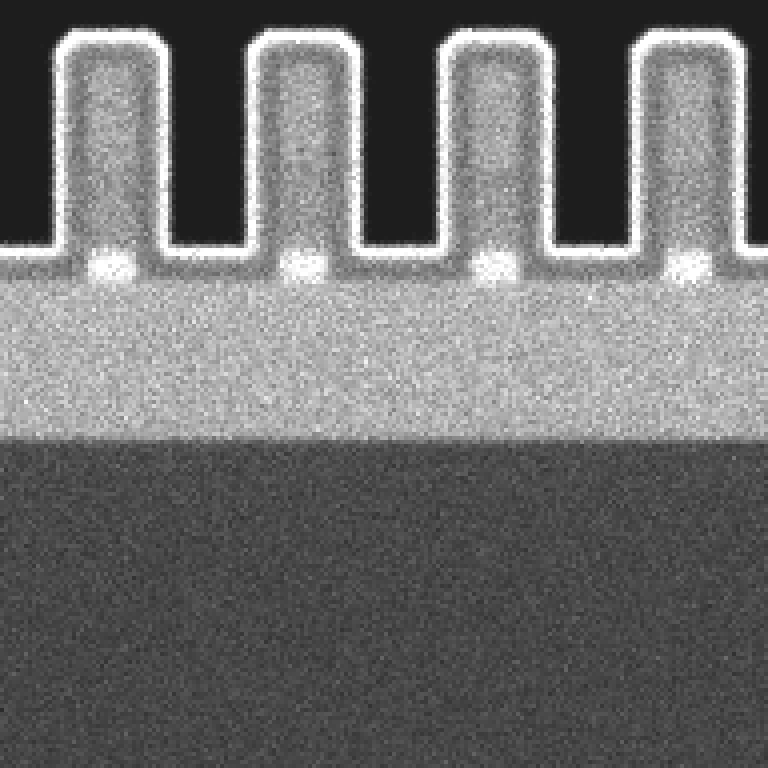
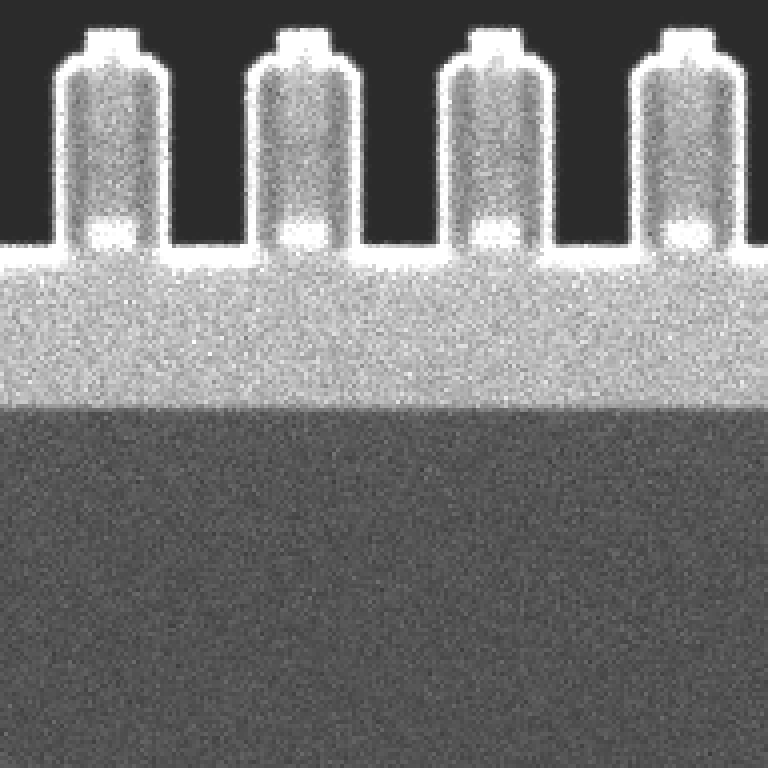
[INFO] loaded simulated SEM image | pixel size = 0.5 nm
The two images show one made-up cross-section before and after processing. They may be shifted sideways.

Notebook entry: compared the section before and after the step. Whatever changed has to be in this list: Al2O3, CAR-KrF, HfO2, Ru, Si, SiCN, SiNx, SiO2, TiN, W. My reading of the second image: SiNx removed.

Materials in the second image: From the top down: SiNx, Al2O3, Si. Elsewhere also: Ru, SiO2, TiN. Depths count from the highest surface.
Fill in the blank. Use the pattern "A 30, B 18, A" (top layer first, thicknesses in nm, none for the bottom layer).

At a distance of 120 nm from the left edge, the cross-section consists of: empty 108, Al2O3 80, Si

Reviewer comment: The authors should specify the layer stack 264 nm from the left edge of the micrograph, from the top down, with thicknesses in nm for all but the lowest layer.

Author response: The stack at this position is empty 12, SiNx 96, Al2O3 80, Si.